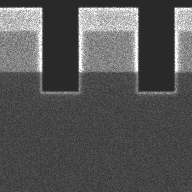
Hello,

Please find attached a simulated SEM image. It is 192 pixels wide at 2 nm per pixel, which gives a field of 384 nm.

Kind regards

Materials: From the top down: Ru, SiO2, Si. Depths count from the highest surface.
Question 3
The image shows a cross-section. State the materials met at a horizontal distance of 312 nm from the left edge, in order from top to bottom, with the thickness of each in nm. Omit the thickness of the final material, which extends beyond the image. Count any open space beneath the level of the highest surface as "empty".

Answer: empty 168, Si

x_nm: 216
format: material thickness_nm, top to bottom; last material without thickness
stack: Ru 46, SiO2 82, Si